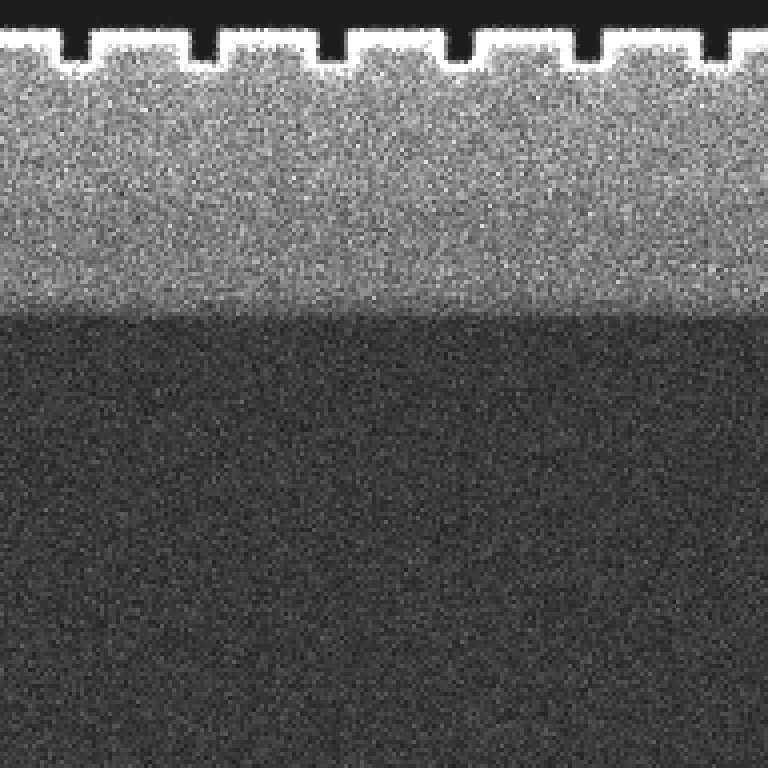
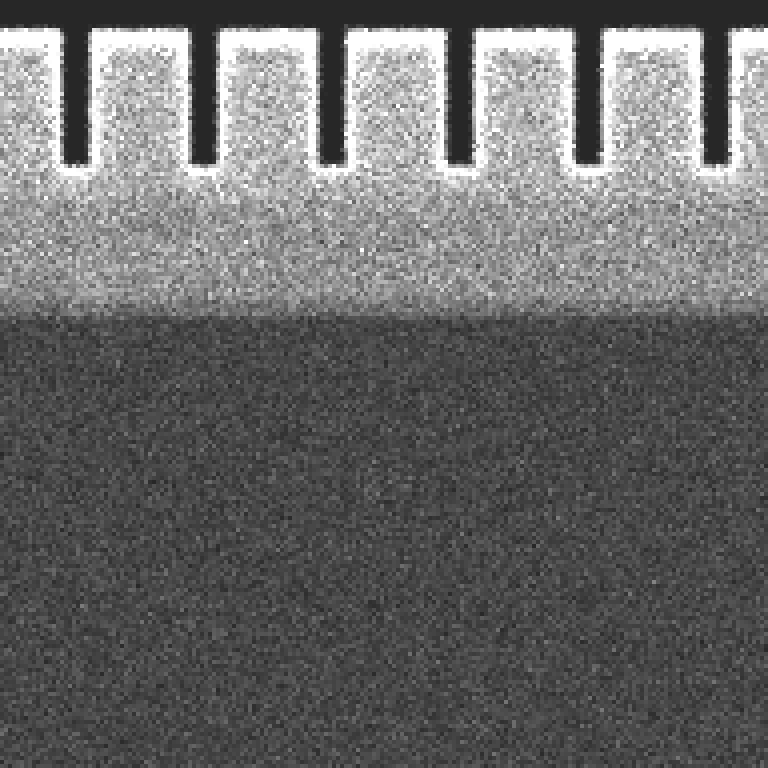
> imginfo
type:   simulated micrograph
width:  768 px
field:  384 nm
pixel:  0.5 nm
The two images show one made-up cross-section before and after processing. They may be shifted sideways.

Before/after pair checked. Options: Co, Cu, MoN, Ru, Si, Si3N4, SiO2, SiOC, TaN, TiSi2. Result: removed Ru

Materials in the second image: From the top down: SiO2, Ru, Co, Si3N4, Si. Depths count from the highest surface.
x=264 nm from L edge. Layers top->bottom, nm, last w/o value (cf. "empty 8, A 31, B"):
SiO2 16, Ru 68, Co 50, Si3N4 8, Si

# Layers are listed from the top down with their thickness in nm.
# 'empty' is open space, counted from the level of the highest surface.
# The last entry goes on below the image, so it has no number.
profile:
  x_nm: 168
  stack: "empty 68, Ru 16, Co 50, Si3N4 8, Si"